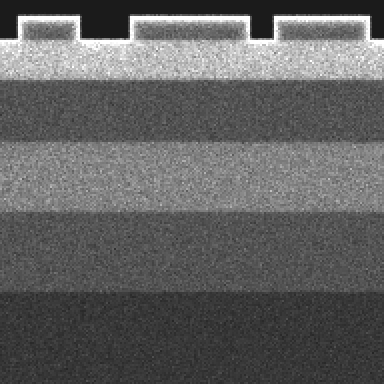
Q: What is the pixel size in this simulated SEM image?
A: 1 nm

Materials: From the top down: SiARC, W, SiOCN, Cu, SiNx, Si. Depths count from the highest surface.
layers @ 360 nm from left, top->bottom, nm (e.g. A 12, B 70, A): SiARC 24, W 40, SiOCN 62, Cu 70, SiNx 80, Si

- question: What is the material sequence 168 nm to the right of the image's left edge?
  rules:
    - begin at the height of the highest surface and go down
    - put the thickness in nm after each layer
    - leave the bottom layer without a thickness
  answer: SiARC 24, W 40, SiOCN 62, Cu 70, SiNx 80, Si